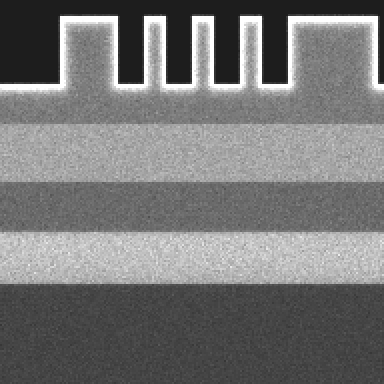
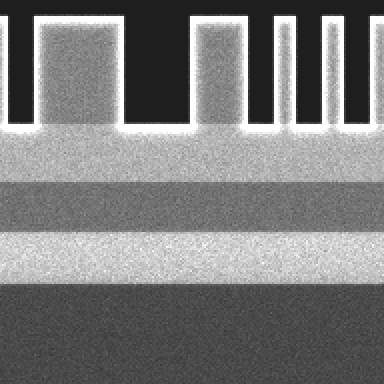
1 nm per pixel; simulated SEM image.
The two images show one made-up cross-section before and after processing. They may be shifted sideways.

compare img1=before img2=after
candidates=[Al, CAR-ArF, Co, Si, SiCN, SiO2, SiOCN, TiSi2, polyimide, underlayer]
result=removed:underlayer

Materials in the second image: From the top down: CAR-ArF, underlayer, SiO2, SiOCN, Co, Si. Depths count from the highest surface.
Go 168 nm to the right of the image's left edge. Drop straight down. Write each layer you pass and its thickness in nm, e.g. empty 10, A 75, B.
empty 108, SiO2 58, SiOCN 50, Co 52, Si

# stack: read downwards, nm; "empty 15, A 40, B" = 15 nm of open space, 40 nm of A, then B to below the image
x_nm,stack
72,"CAR-ArF 68, underlayer 40, SiO2 58, SiOCN 50, Co 52, Si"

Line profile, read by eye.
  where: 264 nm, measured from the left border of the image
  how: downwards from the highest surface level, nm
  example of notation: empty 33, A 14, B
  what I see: empty 108, SiO2 58, SiOCN 50, Co 52, Si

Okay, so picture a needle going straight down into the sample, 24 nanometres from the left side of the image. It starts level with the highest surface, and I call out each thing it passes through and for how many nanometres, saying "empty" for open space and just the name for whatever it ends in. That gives empty 108, SiO2 58, SiOCN 50, Co 52, Si